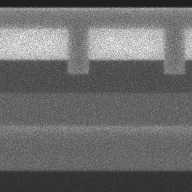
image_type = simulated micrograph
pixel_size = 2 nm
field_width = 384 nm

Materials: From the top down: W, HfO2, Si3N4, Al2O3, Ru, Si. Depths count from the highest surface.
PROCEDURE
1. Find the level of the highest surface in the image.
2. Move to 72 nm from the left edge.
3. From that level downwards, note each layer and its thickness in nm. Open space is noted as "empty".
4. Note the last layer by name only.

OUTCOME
W 42, HfO2 62, Si3N4 66, Al2O3 66, Ru 90, Si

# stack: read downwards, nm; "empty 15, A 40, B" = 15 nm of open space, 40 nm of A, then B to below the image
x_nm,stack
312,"W 42, HfO2 62, Si3N4 66, Al2O3 66, Ru 90, Si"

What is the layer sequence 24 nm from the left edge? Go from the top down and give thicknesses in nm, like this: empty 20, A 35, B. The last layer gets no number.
W 42, HfO2 62, Si3N4 66, Al2O3 66, Ru 90, Si